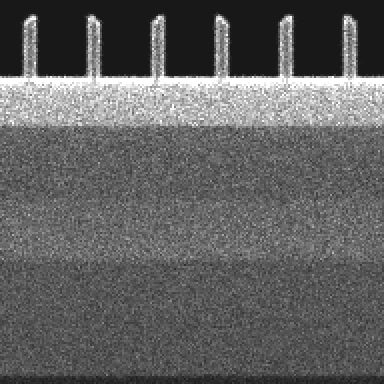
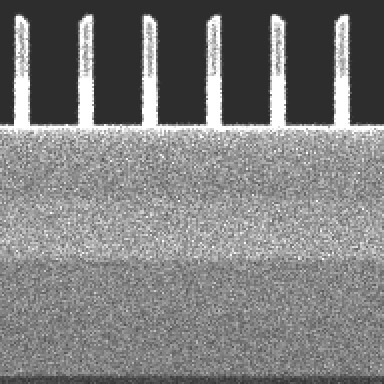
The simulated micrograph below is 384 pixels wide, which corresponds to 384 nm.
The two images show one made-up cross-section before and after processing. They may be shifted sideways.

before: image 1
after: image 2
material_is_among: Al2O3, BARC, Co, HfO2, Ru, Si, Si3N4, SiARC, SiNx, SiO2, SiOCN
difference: HfO2, removed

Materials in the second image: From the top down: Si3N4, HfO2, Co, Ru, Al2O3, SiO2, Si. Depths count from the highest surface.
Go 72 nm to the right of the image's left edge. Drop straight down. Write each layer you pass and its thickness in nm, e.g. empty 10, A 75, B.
empty 110, Co 74, Ru 60, Al2O3 54, SiO2 62, Si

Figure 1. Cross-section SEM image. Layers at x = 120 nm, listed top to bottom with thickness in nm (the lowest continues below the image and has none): empty 110, Co 74, Ru 60, Al2O3 54, SiO2 62, Si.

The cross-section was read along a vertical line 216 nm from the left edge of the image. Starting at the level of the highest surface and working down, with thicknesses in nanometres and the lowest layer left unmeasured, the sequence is Si3N4 62, HfO2 48, Co 74, Ru 60, Al2O3 54, SiO2 62, Si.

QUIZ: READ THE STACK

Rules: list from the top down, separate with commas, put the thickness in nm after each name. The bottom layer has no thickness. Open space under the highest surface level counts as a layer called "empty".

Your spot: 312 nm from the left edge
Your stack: empty 110, Co 74, Ru 60, Al2O3 54, SiO2 62, Si